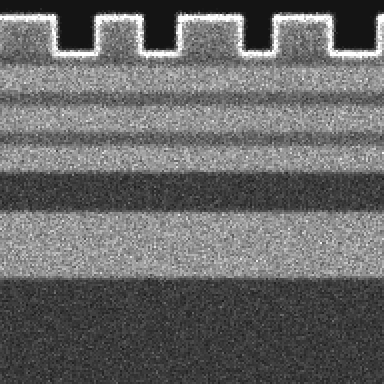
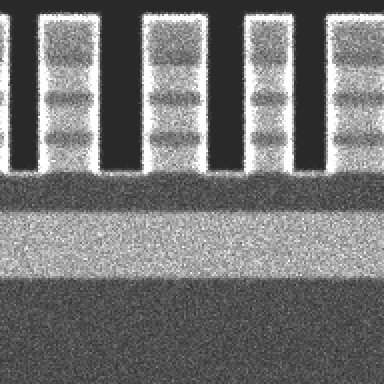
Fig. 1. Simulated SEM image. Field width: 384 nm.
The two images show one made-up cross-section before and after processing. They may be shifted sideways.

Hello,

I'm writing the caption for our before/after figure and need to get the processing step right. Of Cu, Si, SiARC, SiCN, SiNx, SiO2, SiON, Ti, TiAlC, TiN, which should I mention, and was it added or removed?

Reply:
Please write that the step removed SiNx and SiO2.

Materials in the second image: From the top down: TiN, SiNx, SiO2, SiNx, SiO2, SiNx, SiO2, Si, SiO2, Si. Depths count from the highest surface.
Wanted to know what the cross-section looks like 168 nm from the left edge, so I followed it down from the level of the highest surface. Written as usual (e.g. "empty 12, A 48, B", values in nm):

TiN 36, SiNx 14, SiO2 26, SiNx 14, SiO2 26, SiNx 14, SiO2 26, Si 40, SiO2 66, Si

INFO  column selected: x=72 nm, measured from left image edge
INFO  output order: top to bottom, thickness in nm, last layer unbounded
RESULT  TiN 36, SiNx 14, SiO2 26, SiNx 14, SiO2 26, SiNx 14, SiO2 26, Si 40, SiO2 66, Si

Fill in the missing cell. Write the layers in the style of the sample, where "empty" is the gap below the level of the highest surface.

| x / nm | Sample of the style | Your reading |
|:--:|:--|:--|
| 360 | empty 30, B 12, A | TiN 36, SiNx 14, SiO2 26, SiNx 14, SiO2 26, SiNx 14, SiO2 26, Si 40, SiO2 66, Si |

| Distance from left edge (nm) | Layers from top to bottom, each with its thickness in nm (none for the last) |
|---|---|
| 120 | empty 156, Si 40, SiO2 66, Si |